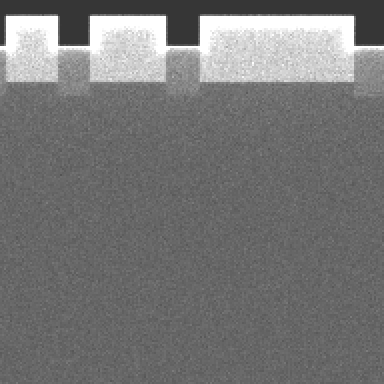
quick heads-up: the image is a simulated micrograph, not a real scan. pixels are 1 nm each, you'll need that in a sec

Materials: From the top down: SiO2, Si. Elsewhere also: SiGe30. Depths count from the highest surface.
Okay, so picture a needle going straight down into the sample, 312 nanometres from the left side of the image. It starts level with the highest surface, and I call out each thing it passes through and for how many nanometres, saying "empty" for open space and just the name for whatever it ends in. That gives SiO2 66, Si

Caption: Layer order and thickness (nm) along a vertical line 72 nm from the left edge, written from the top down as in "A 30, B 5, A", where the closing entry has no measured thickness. empty 30, SiGe30 50, Si